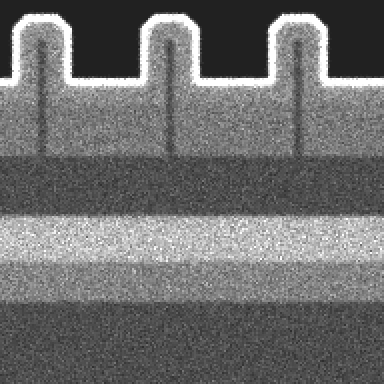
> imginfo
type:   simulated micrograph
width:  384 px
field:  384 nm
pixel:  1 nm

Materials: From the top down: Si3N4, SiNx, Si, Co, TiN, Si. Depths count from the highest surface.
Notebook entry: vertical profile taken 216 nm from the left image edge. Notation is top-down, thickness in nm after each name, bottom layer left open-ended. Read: empty 64, Si3N4 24, SiNx 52, Si 60, Co 46, TiN 40, Si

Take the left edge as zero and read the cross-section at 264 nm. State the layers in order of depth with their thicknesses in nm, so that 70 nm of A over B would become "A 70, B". empty 64, Si3N4 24, SiNx 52, Si 60, Co 46, TiN 40, Si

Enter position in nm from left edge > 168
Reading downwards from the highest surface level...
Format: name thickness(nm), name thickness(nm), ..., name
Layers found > Si3N4 24, Si 176, Co 46, TiN 40, Si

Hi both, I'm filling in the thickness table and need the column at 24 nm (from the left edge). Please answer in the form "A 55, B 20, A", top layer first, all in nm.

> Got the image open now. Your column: empty 2, Si3N4 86, SiNx 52, Si 60, Co 46, TiN 40, Si